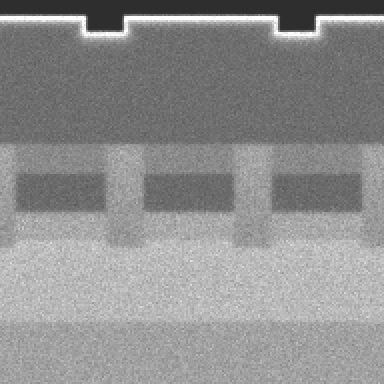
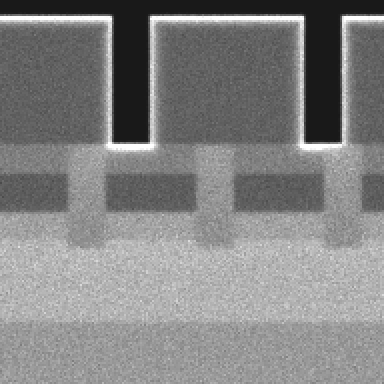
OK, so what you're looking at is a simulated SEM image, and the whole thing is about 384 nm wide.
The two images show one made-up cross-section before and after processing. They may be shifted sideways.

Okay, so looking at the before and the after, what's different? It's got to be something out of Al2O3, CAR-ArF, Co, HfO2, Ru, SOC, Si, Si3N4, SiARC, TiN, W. SOC, removed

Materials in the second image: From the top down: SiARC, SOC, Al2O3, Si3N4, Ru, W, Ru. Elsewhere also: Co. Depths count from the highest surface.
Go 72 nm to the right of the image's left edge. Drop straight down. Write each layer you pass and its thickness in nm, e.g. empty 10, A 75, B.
SiARC 16, SOC 112, Co 104, W 74, Ru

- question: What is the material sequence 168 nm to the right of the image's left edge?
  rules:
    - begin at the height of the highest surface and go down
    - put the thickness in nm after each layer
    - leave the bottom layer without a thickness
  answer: SiARC 16, SOC 112, Al2O3 30, Si3N4 38, Ru 28, W 82, Ru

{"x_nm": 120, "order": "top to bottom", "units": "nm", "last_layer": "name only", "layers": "empty 128, Al2O3 30, Si3N4 38, Ru 28, W 82, Ru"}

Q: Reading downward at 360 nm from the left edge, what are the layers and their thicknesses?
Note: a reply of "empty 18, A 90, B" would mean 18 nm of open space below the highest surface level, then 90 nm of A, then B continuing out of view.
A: SiARC 16, SOC 112, Co 104, W 74, Ru